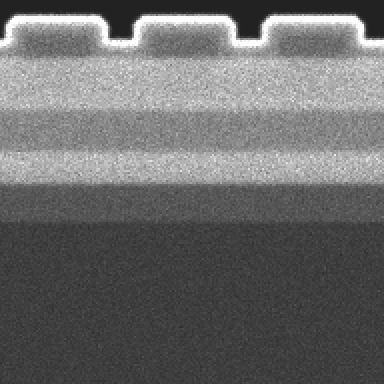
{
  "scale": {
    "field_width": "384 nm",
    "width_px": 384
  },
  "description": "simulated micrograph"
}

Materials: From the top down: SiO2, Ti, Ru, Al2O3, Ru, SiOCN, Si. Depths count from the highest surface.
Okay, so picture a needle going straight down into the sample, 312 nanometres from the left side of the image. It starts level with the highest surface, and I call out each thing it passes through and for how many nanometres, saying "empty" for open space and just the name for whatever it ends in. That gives SiO2 18, Ti 24, Ru 52, Al2O3 42, Ru 32, SiOCN 38, Si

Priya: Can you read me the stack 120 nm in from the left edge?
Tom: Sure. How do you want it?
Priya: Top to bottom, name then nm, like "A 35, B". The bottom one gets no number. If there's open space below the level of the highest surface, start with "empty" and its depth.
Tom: empty 24, SiO2 18, Ru 52, Al2O3 42, Ru 32, SiOCN 38, Si